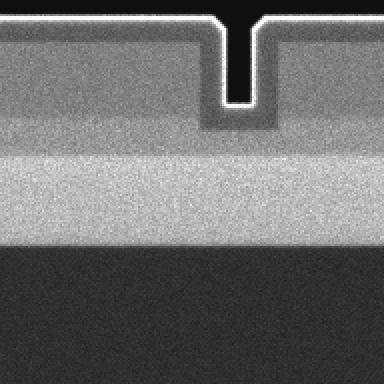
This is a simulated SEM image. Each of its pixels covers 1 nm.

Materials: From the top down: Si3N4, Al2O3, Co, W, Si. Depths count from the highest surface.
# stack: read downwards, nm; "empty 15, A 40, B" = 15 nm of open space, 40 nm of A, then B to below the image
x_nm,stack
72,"Si3N4 26, Al2O3 76, Co 38, W 90, Si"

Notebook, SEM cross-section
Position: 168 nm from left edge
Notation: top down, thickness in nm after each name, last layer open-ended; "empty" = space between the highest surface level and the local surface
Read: Si3N4 26, Al2O3 76, Co 38, W 90, Si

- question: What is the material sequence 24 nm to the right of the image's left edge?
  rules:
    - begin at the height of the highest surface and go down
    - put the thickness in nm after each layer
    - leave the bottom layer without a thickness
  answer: Si3N4 26, Al2O3 76, Co 38, W 90, Si